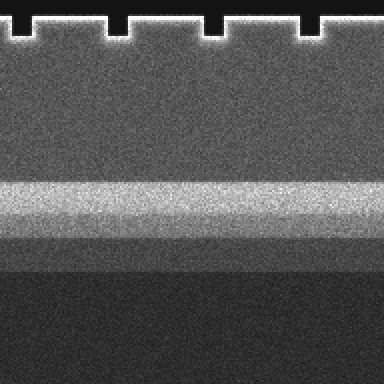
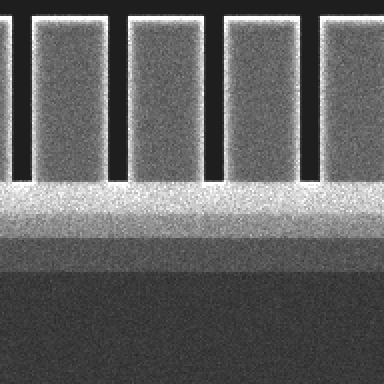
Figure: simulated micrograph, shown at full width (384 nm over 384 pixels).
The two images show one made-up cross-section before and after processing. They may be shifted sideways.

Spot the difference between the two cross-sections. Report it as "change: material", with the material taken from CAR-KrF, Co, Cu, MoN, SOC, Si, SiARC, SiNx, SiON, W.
removed: SOC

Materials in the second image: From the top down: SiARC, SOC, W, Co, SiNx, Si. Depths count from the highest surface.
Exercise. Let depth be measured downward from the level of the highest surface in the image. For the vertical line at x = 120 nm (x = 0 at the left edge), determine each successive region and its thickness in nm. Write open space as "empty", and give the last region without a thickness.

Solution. empty 166, W 32, Co 24, SiNx 34, Si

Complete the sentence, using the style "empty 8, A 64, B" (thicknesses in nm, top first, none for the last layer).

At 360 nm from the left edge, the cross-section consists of SiARC 20, SOC 146, W 32, Co 24, SiNx 34, Si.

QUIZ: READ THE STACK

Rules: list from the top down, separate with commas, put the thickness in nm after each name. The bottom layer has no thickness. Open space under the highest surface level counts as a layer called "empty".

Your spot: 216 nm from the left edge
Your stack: empty 166, W 32, Co 24, SiNx 34, Si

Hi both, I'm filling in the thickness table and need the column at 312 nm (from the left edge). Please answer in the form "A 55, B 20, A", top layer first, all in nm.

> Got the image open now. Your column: empty 166, W 32, Co 24, SiNx 34, Si